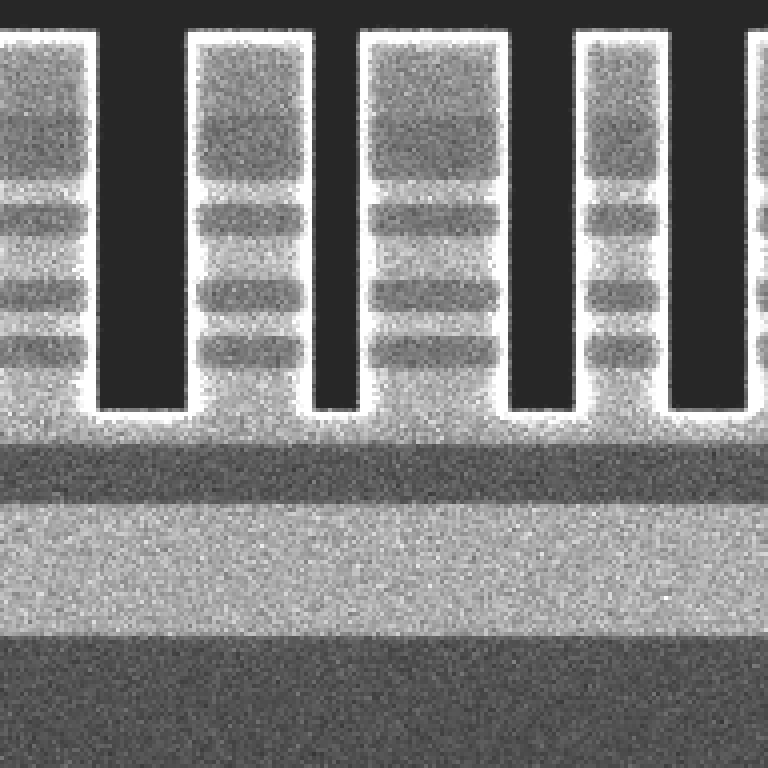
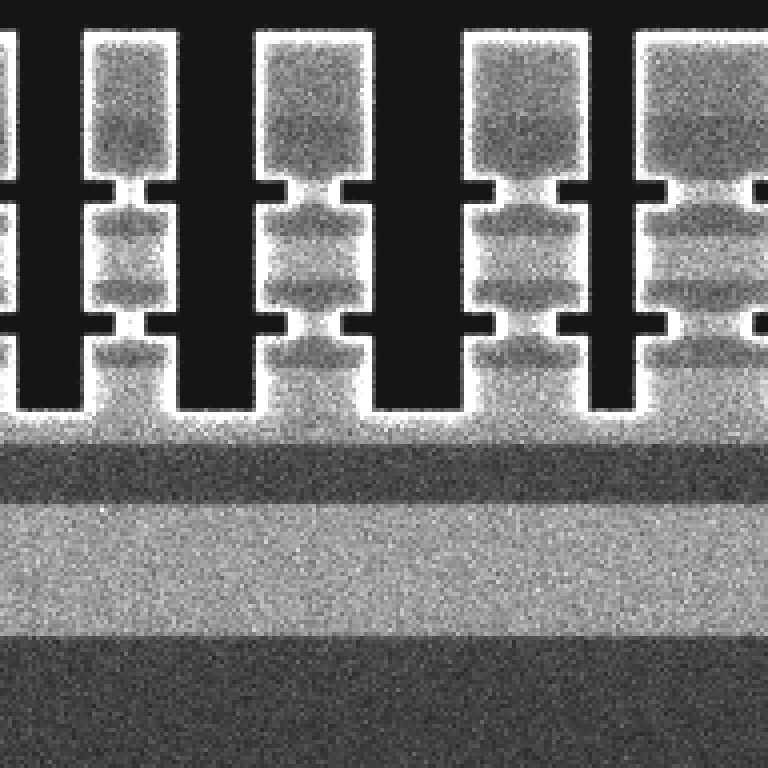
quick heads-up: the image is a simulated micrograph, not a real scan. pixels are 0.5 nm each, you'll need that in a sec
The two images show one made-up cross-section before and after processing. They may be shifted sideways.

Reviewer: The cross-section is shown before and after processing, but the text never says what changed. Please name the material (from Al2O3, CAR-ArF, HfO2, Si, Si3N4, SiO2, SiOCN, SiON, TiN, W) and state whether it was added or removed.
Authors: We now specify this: Al2O3, removed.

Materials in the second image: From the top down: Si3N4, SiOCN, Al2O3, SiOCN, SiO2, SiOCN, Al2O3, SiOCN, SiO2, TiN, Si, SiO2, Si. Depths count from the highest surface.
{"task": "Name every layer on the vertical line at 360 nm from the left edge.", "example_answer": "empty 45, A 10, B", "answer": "Si3N4 42, SiOCN 32, Al2O3 12, SiOCN 16, SiO2 22, SiOCN 16, Al2O3 12, SiOCN 16, SiO2 22, TiN 16, Si 30, SiO2 66, Si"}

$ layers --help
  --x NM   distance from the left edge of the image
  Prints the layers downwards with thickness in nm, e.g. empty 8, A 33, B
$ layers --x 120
empty 190, TiN 16, Si 30, SiO2 66, Si